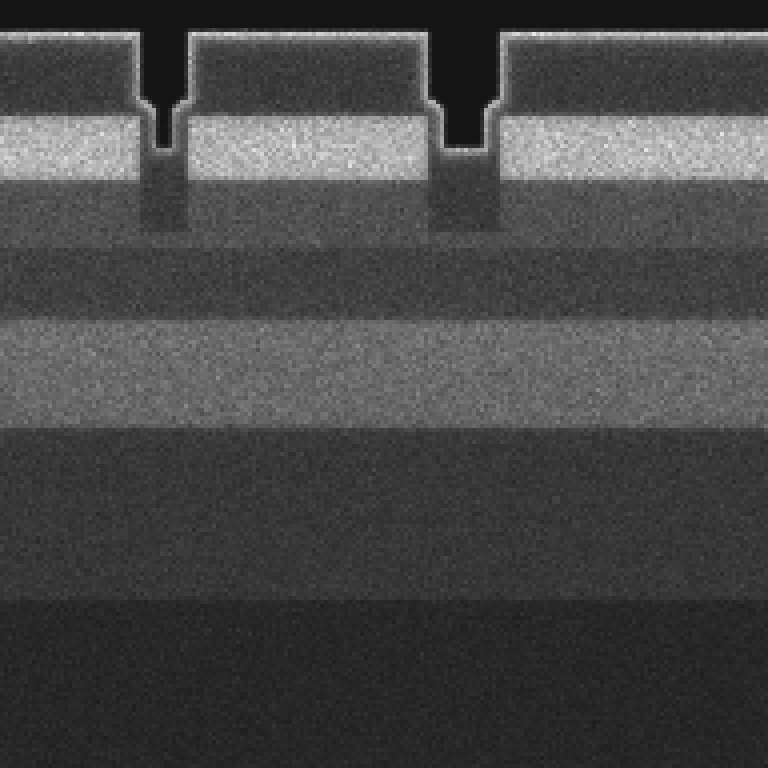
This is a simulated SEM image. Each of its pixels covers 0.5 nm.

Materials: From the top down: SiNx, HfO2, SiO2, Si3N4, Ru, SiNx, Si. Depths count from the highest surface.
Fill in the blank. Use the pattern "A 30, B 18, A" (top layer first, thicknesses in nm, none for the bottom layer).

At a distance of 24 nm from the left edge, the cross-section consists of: SiNx 42, HfO2 32, SiO2 34, Si3N4 36, Ru 54, SiNx 86, Si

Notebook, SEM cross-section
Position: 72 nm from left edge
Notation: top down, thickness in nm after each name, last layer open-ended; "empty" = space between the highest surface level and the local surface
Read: empty 34, SiNx 66, SiO2 8, Si3N4 36, Ru 54, SiNx 86, Si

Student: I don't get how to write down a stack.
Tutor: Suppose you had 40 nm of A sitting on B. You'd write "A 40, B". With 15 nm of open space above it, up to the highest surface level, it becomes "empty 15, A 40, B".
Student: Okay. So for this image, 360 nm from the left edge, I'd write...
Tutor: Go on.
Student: SiNx 42, HfO2 32, SiO2 34, Si3N4 36, Ru 54, SiNx 86, Si